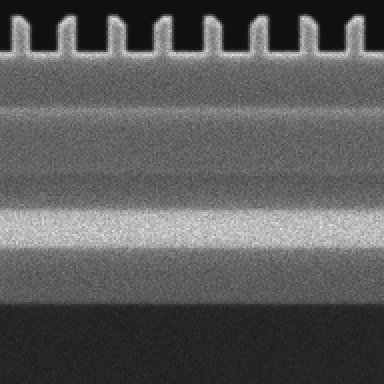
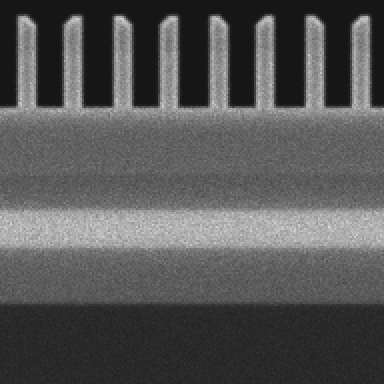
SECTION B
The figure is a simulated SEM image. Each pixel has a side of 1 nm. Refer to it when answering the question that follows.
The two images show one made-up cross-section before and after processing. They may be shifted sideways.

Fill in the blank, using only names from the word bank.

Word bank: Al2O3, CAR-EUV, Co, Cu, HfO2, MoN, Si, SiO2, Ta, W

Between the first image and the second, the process removed Al2O3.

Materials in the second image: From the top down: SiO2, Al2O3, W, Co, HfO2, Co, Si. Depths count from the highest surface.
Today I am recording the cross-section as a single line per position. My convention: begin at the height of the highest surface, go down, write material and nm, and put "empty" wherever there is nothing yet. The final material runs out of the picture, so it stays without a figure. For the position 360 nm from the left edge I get SiO2 36, Al2O3 56, W 66, Co 36, HfO2 38, Co 56, Si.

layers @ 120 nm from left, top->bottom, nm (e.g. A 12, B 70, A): SiO2 36, Al2O3 56, W 66, Co 36, HfO2 38, Co 56, Si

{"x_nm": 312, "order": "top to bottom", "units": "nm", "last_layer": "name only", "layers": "SiO2 36, Al2O3 56, W 66, Co 36, HfO2 38, Co 56, Si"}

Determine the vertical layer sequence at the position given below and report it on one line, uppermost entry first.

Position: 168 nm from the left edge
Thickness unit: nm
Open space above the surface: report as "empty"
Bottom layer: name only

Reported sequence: SiO2 36, Al2O3 56, W 66, Co 36, HfO2 38, Co 56, Si